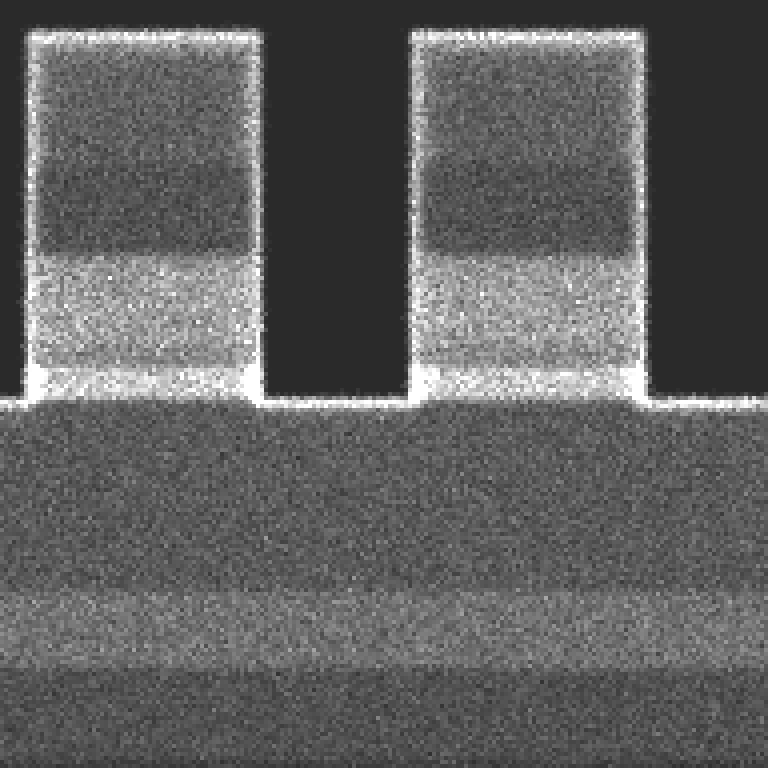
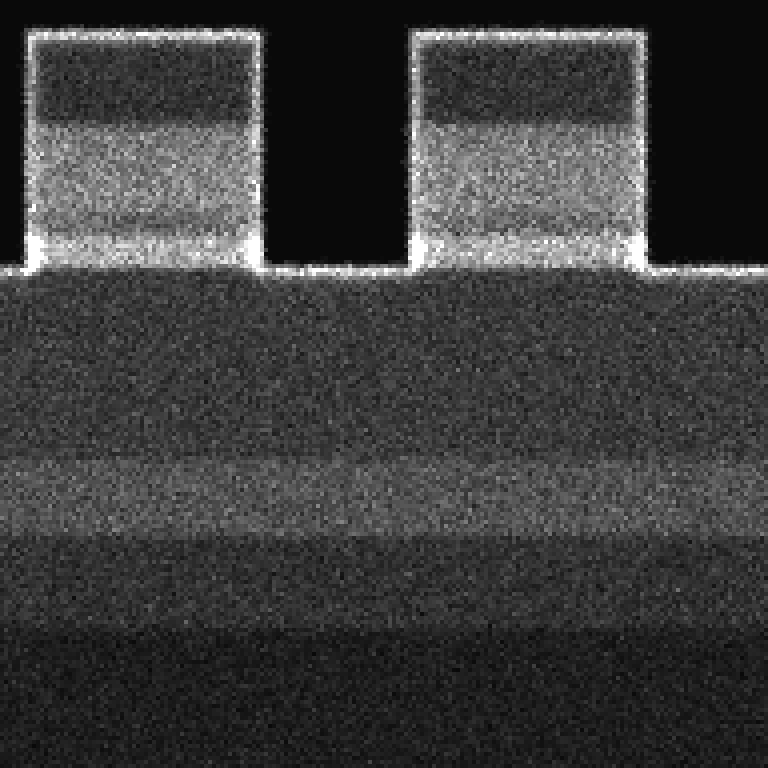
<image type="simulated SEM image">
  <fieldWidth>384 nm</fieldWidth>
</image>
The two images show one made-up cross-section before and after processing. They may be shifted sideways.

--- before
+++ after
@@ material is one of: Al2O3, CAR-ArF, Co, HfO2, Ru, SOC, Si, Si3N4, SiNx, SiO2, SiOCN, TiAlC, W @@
SOC removed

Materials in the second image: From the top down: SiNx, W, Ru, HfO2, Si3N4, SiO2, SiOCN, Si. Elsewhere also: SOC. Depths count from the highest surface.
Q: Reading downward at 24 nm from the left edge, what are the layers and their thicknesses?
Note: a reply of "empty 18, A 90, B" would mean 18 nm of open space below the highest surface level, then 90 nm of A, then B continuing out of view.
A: SiNx 46, W 44, Ru 12, HfO2 16, Si3N4 96, SiO2 38, SiOCN 46, Si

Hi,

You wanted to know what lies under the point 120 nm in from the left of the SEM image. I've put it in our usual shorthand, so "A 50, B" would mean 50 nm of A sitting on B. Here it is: SiNx 46, W 44, Ru 12, HfO2 16, Si3N4 96, SiO2 38, SiOCN 46, Si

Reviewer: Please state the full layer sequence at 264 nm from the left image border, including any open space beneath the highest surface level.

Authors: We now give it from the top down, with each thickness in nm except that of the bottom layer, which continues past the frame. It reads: SiNx 46, W 44, Ru 12, HfO2 16, Si3N4 96, SiO2 38, SiOCN 46, Si